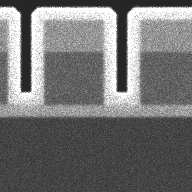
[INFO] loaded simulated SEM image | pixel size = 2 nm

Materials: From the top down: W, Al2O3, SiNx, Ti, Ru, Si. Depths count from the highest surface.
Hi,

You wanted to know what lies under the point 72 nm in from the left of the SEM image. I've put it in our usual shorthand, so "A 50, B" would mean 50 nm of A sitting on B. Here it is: empty 4, W 190, Ru 24, Si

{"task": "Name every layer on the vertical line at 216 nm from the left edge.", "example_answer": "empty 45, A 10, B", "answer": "W 194, Ru 24, Si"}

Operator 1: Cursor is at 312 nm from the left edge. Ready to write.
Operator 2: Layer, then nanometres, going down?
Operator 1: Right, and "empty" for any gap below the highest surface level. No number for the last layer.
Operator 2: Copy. W 24, Al2O3 64, SiNx 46, Ti 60, Ru 24, Si